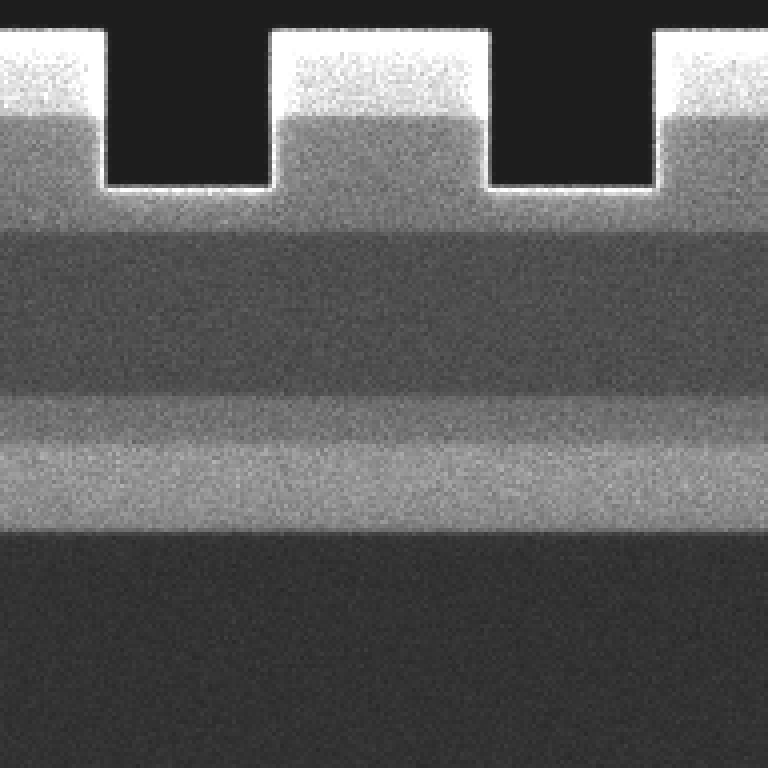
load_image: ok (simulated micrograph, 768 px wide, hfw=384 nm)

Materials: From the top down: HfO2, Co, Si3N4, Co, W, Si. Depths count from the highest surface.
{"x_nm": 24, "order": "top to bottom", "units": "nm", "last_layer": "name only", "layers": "HfO2 42, Co 58, Si3N4 82, Co 24, W 44, Si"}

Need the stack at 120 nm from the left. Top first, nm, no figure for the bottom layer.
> empty 78, Co 22, Si3N4 82, Co 24, W 44, Si